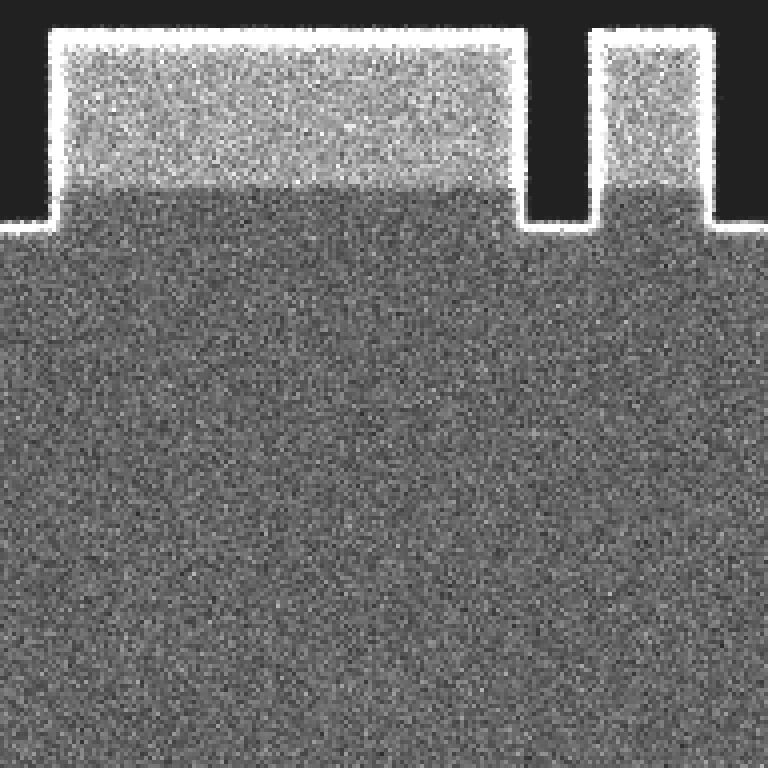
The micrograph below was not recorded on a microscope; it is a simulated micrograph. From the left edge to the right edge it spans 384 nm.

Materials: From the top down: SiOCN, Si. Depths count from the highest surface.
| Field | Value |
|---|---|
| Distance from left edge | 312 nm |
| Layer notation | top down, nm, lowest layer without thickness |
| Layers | SiOCN 78, Si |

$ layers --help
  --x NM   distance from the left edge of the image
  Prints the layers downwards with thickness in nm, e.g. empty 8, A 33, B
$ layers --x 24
empty 96, Si